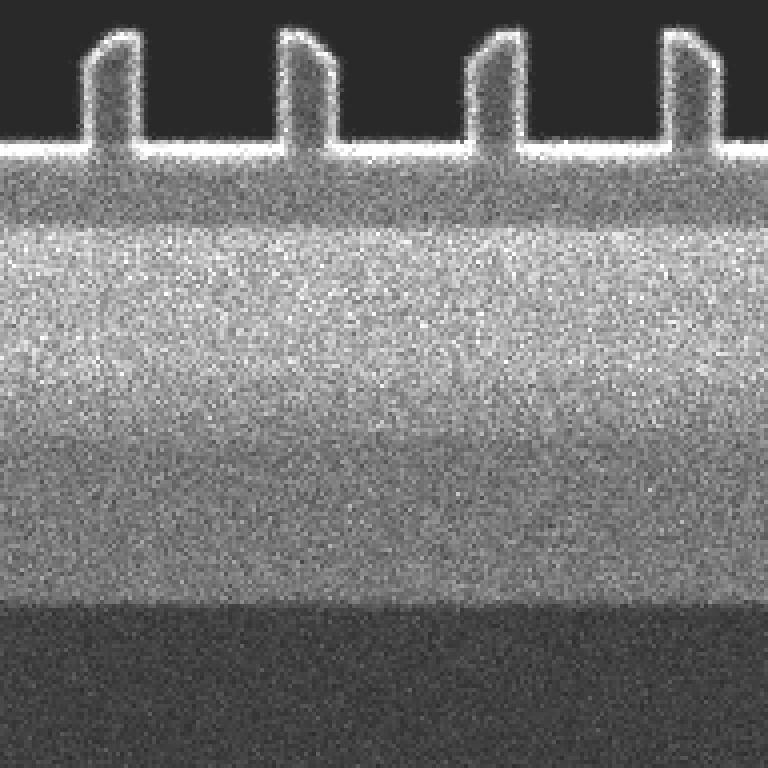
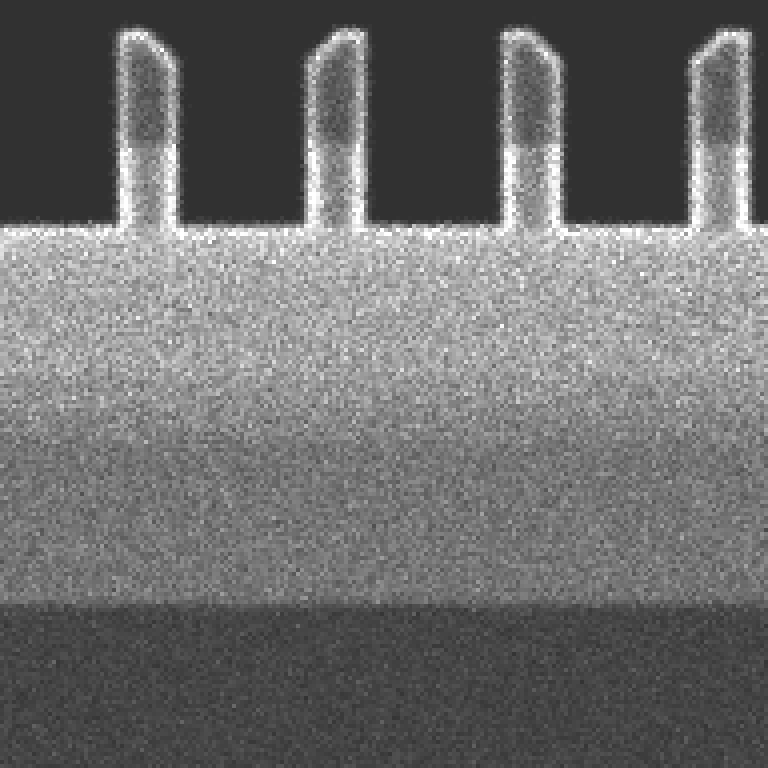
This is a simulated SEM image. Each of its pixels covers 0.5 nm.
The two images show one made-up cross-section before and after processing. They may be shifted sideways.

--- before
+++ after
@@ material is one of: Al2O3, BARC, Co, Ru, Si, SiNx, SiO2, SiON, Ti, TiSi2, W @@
Al2O3 removed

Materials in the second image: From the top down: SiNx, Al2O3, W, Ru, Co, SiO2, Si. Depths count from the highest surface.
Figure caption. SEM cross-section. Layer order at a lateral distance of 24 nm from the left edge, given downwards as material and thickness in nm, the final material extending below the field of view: empty 98, W 74, Ru 16, Co 16, SiO2 82, Si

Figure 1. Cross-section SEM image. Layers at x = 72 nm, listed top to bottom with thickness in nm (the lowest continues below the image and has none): SiNx 56, Al2O3 42, W 74, Ru 16, Co 16, SiO2 82, Si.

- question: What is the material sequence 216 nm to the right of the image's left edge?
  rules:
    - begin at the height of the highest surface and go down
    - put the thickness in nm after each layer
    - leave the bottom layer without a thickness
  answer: empty 98, W 74, Ru 16, Co 16, SiO2 82, Si